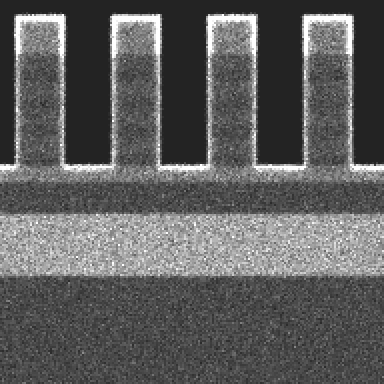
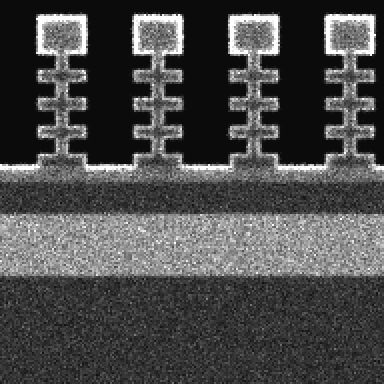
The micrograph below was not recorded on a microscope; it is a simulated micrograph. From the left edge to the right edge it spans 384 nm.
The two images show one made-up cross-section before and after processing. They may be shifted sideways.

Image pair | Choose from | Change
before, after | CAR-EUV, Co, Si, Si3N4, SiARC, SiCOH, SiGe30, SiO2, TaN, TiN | SiGe30 (removed)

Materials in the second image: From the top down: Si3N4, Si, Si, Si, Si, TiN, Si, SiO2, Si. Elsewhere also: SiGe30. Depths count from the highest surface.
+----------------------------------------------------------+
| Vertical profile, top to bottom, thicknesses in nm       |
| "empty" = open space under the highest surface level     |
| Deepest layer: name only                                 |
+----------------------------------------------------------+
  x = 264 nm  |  Si3N4 38, empty 16, Si 12, empty 16, Si 12, empty 16, Si 12, empty 16, Si 12, TiN 16, Si 32, SiO2 62, Si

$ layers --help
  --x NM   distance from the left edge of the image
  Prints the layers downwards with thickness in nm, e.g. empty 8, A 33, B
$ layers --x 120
empty 150, TiN 16, Si 32, SiO2 62, Si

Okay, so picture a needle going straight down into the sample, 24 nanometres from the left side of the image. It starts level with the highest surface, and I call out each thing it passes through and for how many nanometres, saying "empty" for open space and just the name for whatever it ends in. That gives empty 150, TiN 16, Si 32, SiO2 62, Si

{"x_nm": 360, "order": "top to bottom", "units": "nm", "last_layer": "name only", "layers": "Si3N4 38, empty 16, Si 12, empty 16, Si 12, empty 16, Si 12, empty 16, Si 12, TiN 16, Si 32, SiO2 62, Si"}